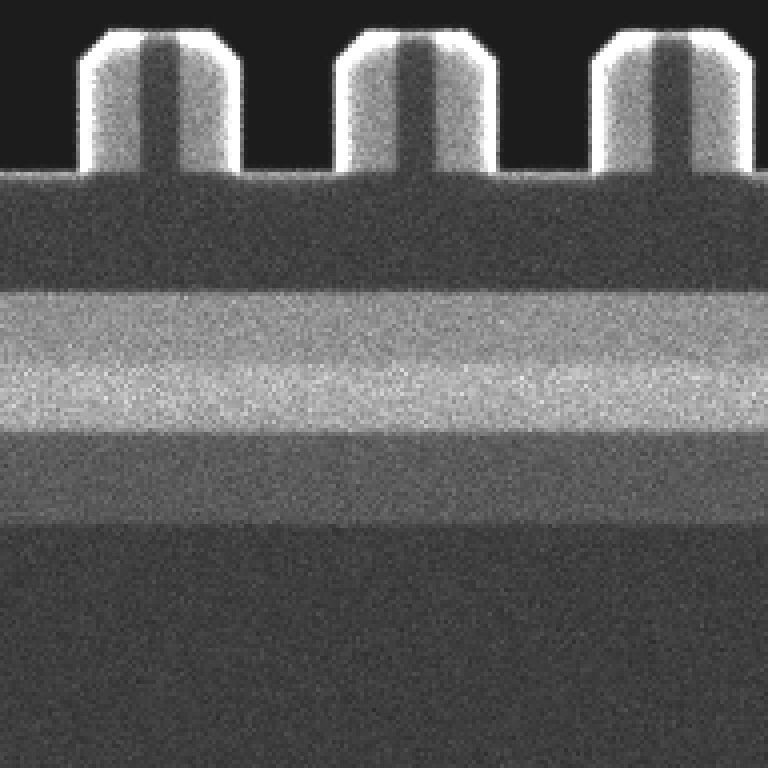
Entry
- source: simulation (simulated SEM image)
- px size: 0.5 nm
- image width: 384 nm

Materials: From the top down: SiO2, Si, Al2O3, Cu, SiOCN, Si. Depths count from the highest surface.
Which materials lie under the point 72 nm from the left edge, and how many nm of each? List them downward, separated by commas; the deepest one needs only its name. Si 130, Al2O3 36, Cu 34, SiOCN 46, Si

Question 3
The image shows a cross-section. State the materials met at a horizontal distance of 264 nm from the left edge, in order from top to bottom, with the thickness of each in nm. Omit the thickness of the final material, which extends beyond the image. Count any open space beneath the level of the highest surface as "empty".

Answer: empty 70, Si 60, Al2O3 36, Cu 34, SiOCN 46, Si